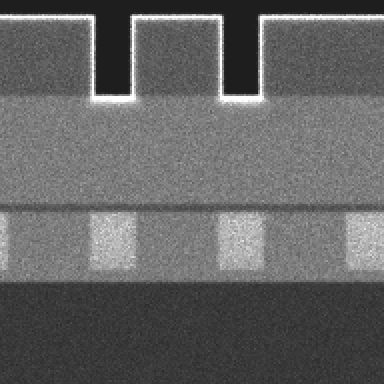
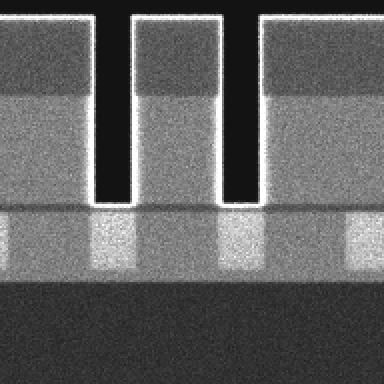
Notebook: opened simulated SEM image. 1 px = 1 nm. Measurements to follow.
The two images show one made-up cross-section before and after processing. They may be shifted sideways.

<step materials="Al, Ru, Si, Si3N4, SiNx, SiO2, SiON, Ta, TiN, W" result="removed SiO2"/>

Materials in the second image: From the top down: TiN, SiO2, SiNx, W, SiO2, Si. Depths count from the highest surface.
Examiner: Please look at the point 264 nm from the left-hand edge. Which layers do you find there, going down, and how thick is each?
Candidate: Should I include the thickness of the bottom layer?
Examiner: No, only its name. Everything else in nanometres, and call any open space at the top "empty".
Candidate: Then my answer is TiN 80, SiO2 108, SiNx 8, SiO2 70, Si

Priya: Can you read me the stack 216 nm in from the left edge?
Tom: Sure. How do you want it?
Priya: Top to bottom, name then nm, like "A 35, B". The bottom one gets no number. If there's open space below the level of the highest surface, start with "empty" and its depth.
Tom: TiN 80, SiO2 108, SiNx 8, SiO2 70, Si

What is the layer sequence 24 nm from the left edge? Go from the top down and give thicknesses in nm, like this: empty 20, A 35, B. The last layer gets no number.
TiN 80, SiO2 108, SiNx 8, SiO2 70, Si